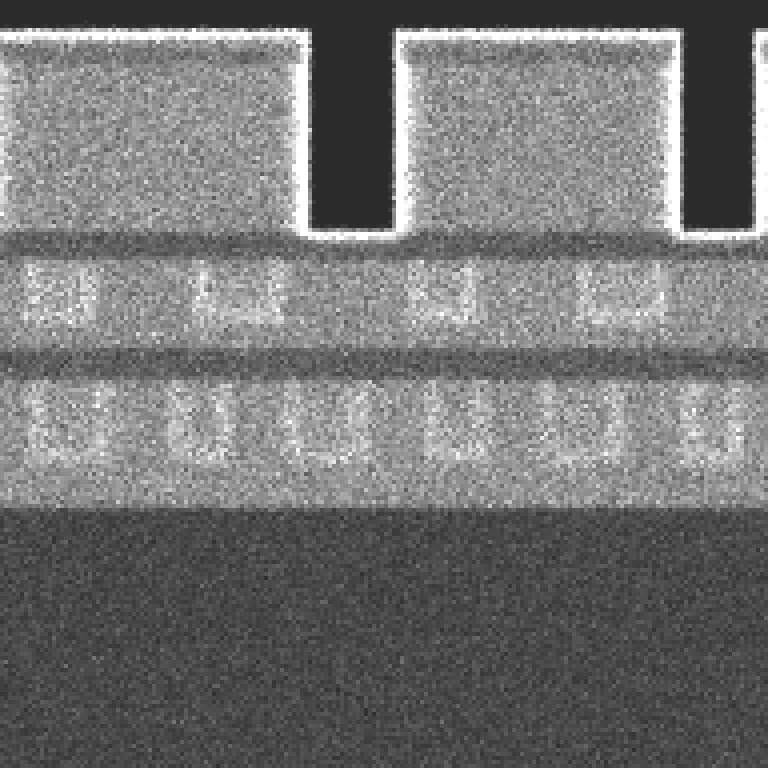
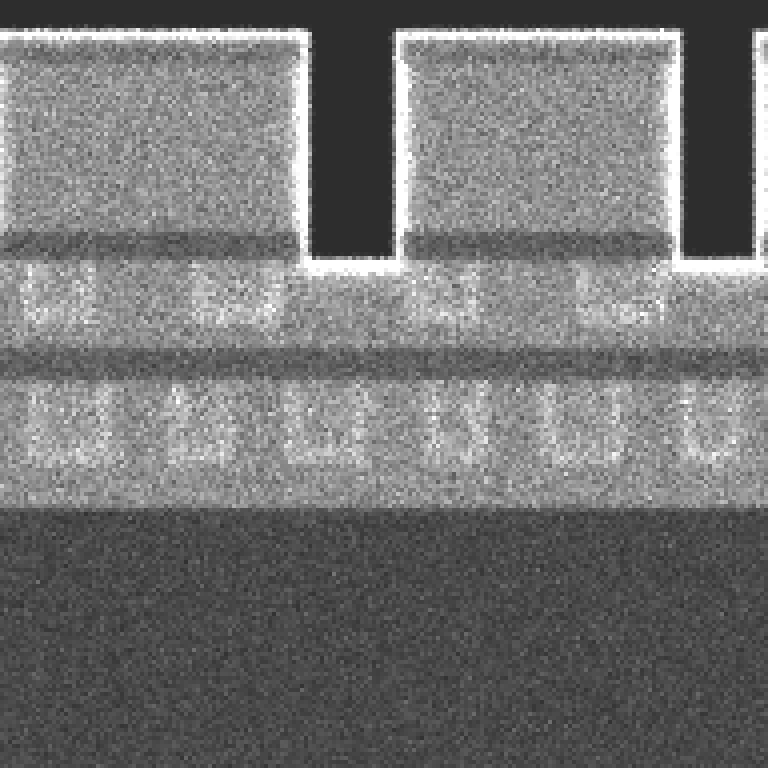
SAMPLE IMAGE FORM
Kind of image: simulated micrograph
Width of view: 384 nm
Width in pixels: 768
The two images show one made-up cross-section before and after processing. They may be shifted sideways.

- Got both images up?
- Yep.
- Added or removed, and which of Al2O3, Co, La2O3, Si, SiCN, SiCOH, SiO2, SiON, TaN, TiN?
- removed, SiCN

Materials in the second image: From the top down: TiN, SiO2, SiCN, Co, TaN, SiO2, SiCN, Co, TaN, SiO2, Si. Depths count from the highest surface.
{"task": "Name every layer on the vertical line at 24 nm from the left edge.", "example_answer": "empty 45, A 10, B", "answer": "TiN 16, SiO2 84, SiCN 14, Co 24, TaN 8, SiO2 12, SiCN 16, Co 34, TaN 8, SiO2 22, Si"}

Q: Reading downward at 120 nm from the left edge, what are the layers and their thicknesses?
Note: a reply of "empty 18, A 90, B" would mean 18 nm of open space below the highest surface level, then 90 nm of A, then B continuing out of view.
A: TiN 16, SiO2 84, SiCN 14, Co 24, TaN 8, SiO2 12, SiCN 16, SiO2 64, Si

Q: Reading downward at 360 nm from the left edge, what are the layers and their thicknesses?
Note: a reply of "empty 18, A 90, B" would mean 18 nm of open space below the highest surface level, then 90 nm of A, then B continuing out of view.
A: empty 114, SiO2 44, SiCN 16, Co 34, TaN 8, SiO2 22, Si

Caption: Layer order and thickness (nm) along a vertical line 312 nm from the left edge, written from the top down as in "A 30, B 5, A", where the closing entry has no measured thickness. TiN 16, SiO2 84, SiCN 14, Co 24, TaN 8, SiO2 12, SiCN 16, SiO2 64, Si